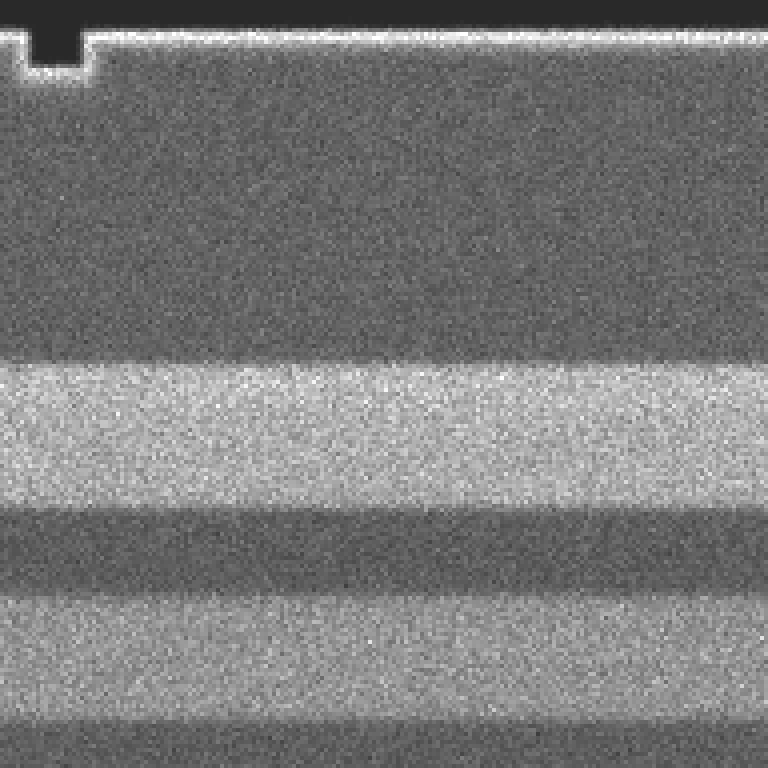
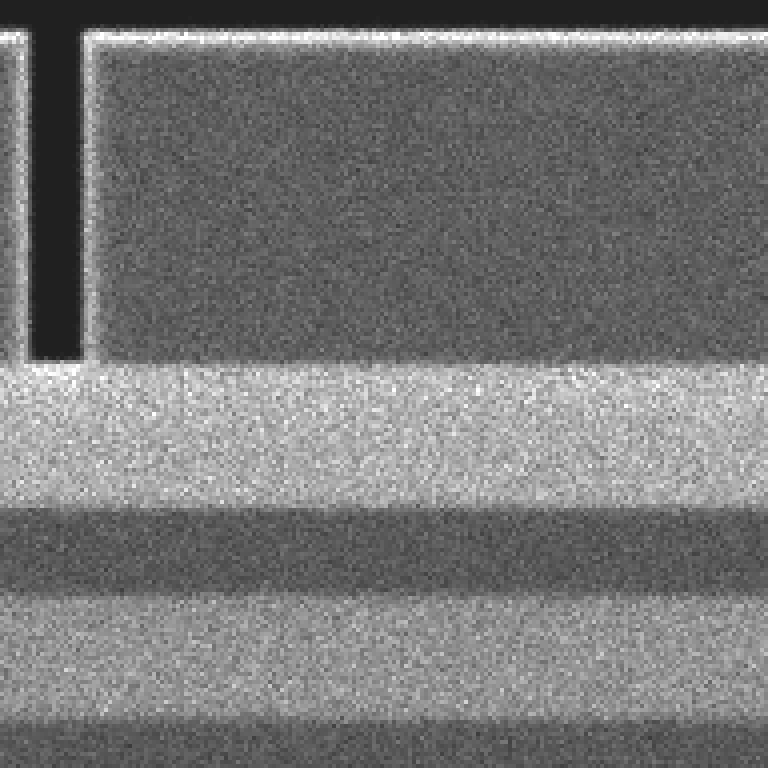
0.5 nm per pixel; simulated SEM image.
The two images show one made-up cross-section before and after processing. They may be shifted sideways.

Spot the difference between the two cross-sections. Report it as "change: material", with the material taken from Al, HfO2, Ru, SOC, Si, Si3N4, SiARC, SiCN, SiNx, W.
removed: SOC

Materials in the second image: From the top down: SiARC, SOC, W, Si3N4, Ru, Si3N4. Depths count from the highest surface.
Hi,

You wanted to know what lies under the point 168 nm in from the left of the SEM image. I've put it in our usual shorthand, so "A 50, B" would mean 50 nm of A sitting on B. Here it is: SiARC 18, SOC 148, W 72, Si3N4 44, Ru 62, Si3N4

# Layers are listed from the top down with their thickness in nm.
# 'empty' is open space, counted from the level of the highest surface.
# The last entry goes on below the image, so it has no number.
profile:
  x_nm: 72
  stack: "SiARC 18, SOC 148, W 72, Si3N4 44, Ru 62, Si3N4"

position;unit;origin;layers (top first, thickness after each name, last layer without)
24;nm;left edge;empty 166, W 72, Si3N4 44, Ru 62, Si3N4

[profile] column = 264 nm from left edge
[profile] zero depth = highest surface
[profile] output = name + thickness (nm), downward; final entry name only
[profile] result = SiARC 18, SOC 148, W 72, Si3N4 44, Ru 62, Si3N4